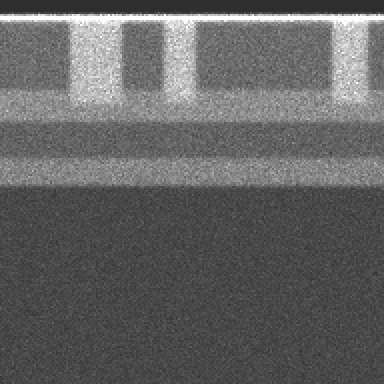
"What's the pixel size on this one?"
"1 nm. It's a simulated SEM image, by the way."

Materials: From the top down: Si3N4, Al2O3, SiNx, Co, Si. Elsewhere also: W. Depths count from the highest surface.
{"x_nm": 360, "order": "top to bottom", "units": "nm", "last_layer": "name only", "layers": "W 88, Al2O3 18, SiNx 36, Co 28, Si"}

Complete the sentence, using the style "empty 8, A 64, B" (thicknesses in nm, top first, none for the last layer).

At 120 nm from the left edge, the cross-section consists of W 88, Al2O3 18, SiNx 36, Co 28, Si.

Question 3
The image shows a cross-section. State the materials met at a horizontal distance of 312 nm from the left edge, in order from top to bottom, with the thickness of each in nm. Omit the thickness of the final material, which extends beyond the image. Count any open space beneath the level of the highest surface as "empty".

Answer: Si3N4 74, Al2O3 32, SiNx 36, Co 28, Si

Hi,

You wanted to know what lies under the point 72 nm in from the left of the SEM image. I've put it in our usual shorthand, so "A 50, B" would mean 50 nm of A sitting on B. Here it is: W 88, Al2O3 18, SiNx 36, Co 28, Si